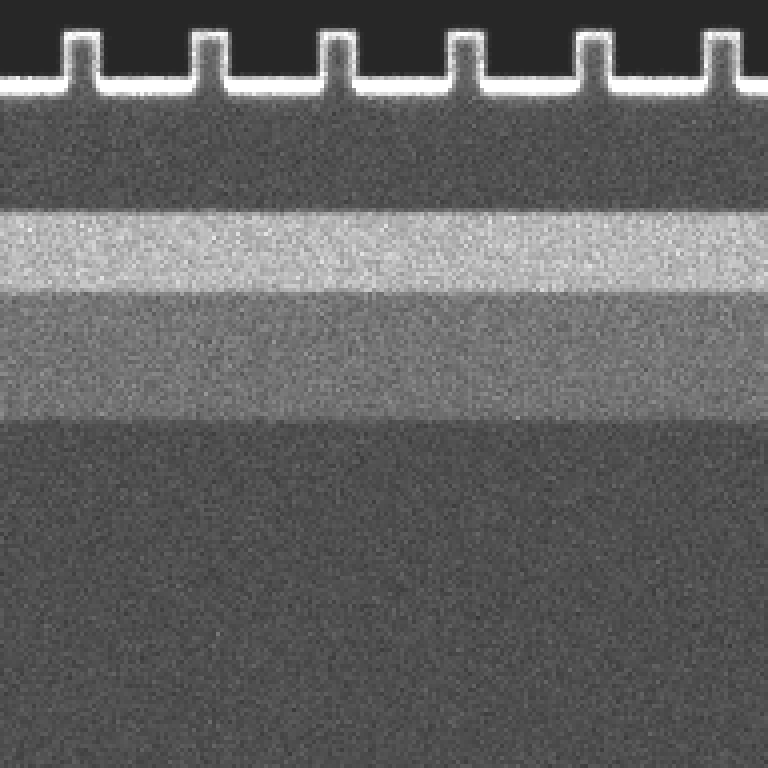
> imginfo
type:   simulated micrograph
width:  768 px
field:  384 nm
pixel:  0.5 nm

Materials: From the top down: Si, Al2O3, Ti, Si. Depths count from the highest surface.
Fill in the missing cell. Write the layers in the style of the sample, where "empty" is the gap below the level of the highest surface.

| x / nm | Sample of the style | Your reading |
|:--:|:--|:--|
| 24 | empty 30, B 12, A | empty 24, Si 66, Al2O3 40, Ti 64, Si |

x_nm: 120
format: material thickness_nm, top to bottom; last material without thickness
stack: empty 24, Si 66, Al2O3 40, Ti 64, Si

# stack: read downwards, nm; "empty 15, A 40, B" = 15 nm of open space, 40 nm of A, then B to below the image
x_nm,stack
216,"empty 24, Si 66, Al2O3 40, Ti 64, Si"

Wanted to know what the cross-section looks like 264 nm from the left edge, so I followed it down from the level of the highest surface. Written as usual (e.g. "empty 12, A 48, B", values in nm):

empty 24, Si 66, Al2O3 40, Ti 64, Si